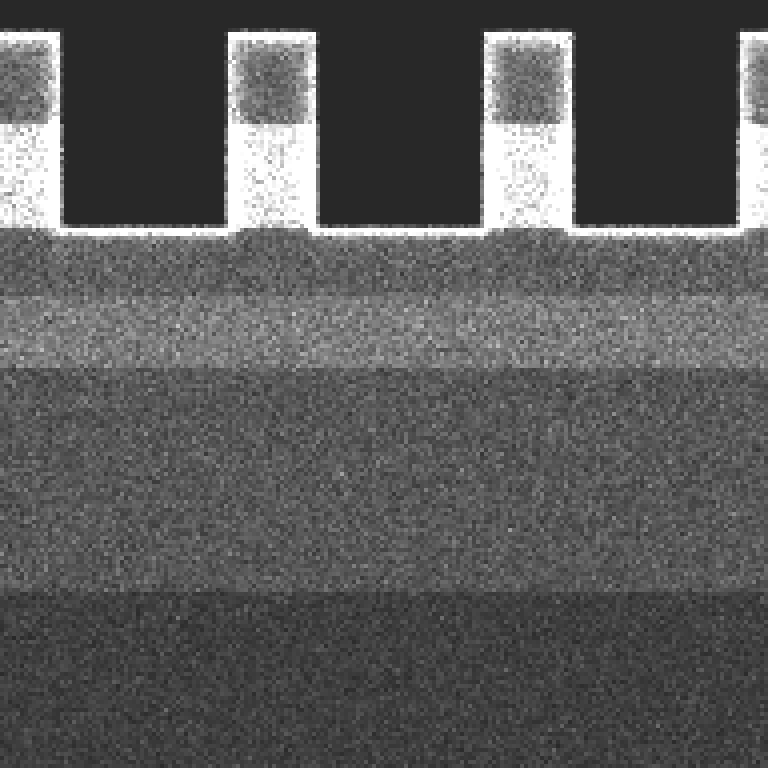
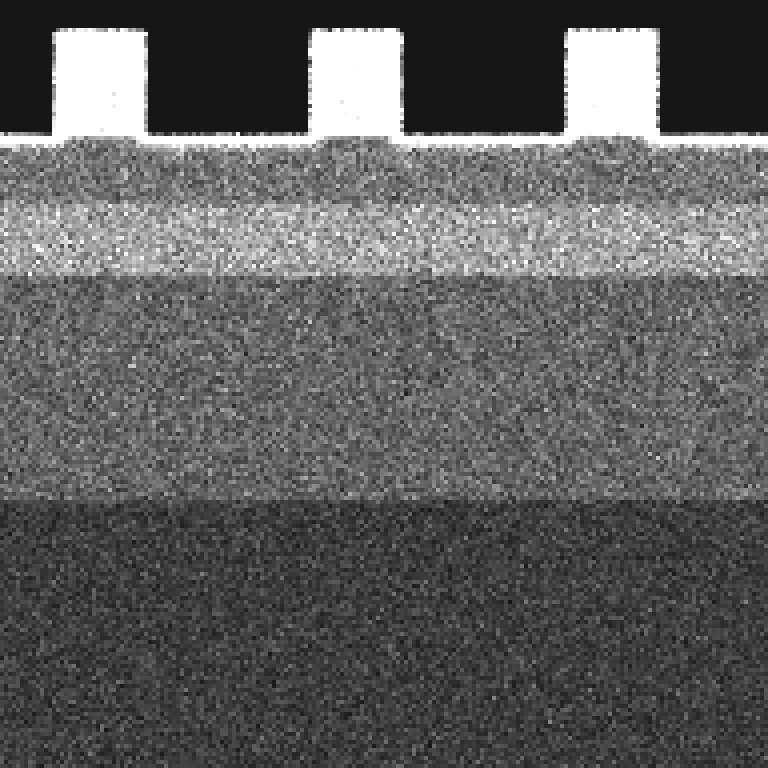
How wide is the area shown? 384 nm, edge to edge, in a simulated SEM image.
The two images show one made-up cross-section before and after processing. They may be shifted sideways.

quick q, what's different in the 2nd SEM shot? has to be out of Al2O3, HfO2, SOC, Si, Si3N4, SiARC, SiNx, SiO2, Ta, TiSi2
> SOC removed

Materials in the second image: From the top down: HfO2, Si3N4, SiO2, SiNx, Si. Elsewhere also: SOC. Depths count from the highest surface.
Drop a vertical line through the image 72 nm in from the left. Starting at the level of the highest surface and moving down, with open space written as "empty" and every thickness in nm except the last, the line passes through empty 52, Si3N4 34, SiO2 36, SiNx 112, Si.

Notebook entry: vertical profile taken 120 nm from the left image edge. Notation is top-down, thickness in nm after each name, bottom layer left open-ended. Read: empty 52, Si3N4 34, SiO2 36, SiNx 112, Si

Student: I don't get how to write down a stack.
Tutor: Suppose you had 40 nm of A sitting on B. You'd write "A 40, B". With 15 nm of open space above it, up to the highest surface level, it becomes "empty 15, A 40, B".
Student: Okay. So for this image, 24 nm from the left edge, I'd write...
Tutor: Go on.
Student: empty 52, Si3N4 34, SiO2 36, SiNx 112, Si